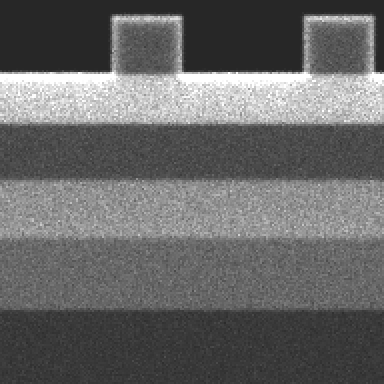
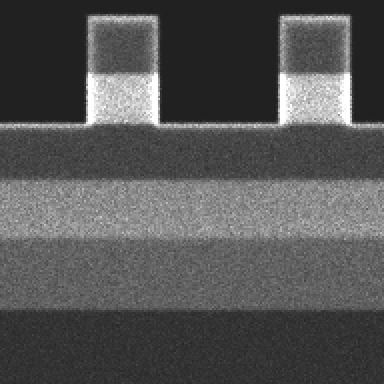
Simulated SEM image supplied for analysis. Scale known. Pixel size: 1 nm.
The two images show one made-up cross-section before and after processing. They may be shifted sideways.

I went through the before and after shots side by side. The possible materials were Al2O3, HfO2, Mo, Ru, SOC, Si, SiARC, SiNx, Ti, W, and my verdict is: removed, HfO2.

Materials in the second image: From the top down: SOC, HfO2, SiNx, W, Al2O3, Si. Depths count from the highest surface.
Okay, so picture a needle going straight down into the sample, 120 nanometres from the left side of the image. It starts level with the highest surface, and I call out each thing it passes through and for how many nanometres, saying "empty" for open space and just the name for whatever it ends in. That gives SOC 58, HfO2 50, SiNx 56, W 58, Al2O3 72, Si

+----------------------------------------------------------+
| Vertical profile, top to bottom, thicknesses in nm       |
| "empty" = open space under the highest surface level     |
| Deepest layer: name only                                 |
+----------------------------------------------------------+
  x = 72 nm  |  empty 108, SiNx 56, W 58, Al2O3 72, Si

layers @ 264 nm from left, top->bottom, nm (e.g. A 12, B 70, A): empty 108, SiNx 56, W 58, Al2O3 72, Si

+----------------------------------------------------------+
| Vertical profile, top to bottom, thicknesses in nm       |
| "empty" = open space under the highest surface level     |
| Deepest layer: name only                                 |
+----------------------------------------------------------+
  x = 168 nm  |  empty 108, SiNx 56, W 58, Al2O3 72, Si